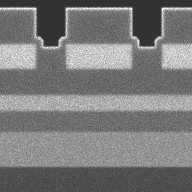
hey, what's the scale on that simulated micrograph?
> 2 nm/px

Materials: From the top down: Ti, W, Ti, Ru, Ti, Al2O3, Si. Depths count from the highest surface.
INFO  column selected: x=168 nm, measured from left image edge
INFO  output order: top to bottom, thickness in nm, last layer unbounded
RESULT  Ti 72, W 50, Ti 52, Ru 32, Ti 42, Al2O3 70, Si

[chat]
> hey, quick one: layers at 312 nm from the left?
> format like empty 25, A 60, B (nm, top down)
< empty 62, Ti 112, Ru 32, Ti 42, Al2O3 70, Si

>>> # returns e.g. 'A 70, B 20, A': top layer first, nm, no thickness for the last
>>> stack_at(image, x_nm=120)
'empty 62, Ti 112, Ru 32, Ti 42, Al2O3 70, Si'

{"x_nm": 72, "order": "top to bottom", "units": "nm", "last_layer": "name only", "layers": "empty 58, Ti 116, Ru 32, Ti 42, Al2O3 70, Si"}